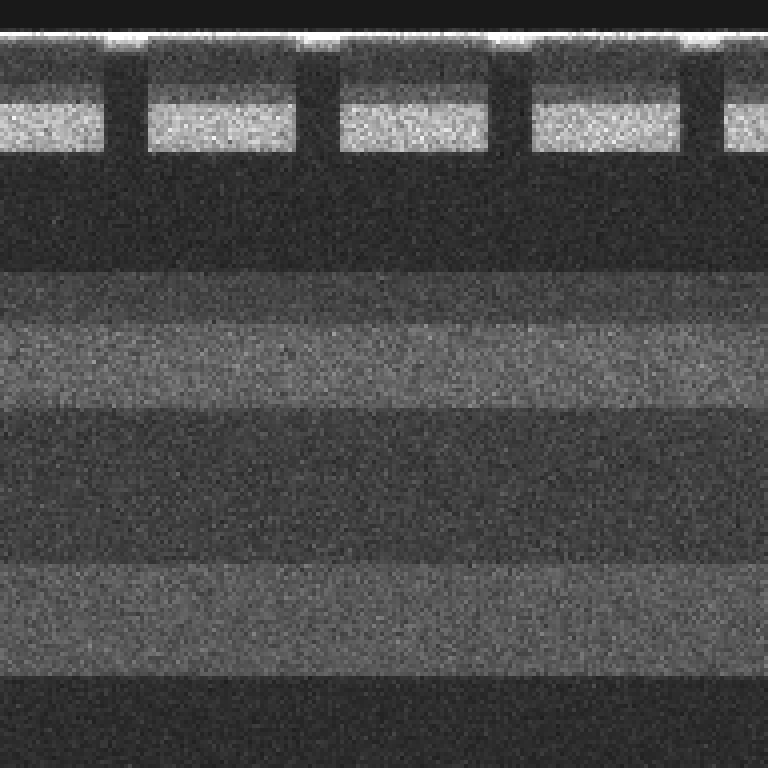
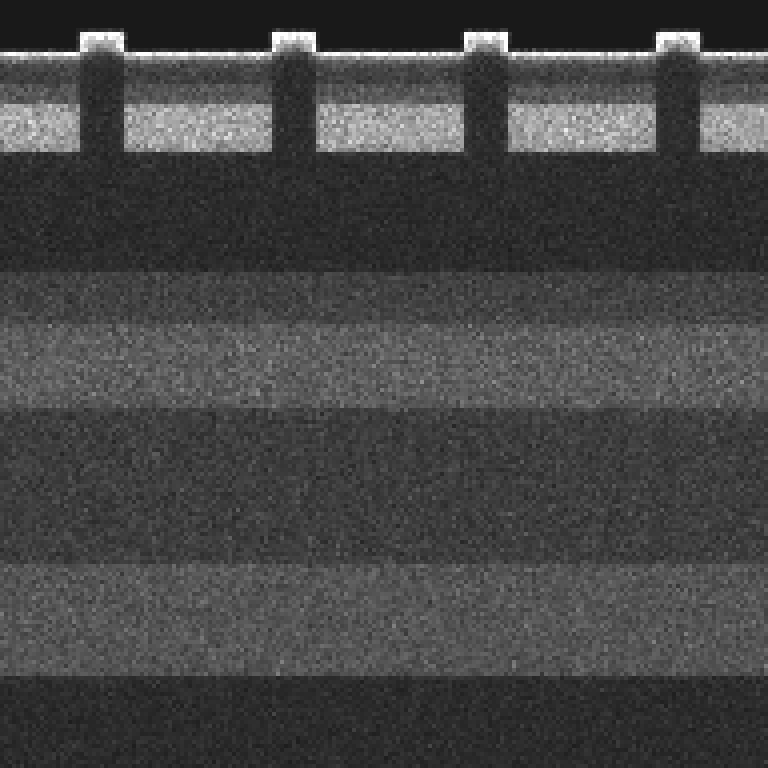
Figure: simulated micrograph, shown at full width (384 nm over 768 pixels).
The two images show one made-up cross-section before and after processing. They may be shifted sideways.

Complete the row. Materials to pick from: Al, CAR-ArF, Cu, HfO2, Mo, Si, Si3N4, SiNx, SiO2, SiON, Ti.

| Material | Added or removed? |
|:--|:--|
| SiNx | removed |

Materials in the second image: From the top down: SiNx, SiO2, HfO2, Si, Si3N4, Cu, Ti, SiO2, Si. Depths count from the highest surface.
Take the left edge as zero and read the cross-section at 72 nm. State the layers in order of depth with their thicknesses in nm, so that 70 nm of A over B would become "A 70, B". empty 10, SiNx 16, SiO2 10, HfO2 24, Si 60, Si3N4 26, Cu 42, Ti 78, SiO2 56, Si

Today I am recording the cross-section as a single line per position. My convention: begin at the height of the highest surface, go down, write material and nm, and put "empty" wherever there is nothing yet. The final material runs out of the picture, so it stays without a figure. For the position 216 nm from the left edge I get empty 10, SiNx 16, SiO2 10, HfO2 24, Si 60, Si3N4 26, Cu 42, Ti 78, SiO2 56, Si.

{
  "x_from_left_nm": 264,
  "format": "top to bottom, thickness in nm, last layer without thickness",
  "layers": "empty 10, SiNx 16, SiO2 10, HfO2 24, Si 60, Si3N4 26, Cu 42, Ti 78, SiO2 56, Si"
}